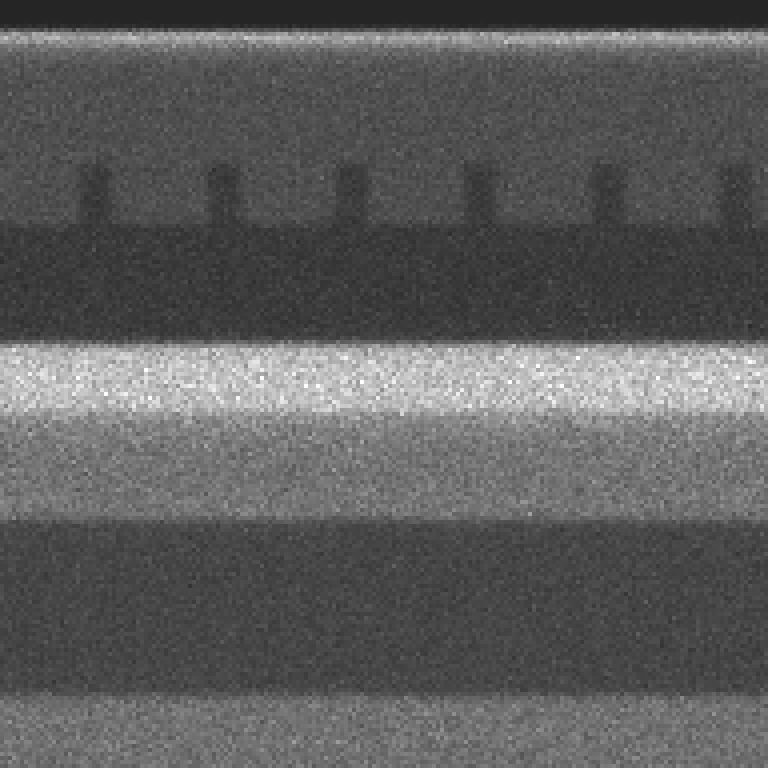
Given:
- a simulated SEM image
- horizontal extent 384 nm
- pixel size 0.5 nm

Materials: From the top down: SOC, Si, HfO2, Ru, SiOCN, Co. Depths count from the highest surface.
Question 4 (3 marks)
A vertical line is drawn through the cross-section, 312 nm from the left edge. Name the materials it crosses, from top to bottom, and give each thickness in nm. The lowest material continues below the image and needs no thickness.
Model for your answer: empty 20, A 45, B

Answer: SOC 96, Si 60, HfO2 34, Ru 54, SiOCN 88, Co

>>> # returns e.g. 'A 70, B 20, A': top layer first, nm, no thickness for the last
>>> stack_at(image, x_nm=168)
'SOC 66, Si 90, HfO2 34, Ru 54, SiOCN 88, Co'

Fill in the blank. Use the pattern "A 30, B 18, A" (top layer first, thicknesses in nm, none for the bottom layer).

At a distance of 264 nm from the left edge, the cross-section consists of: SOC 96, Si 60, HfO2 34, Ru 54, SiOCN 88, Co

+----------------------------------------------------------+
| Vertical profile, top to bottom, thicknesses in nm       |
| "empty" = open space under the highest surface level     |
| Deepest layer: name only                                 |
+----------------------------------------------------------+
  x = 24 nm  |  SOC 96, Si 60, HfO2 34, Ru 54, SiOCN 88, Co